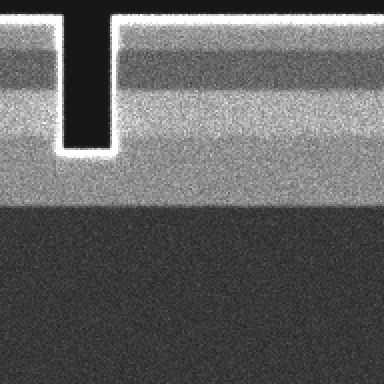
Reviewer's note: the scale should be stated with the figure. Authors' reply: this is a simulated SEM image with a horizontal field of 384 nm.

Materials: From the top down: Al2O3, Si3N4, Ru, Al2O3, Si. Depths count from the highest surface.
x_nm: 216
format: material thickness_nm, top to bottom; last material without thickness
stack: Al2O3 34, Si3N4 40, Ru 46, Al2O3 70, Si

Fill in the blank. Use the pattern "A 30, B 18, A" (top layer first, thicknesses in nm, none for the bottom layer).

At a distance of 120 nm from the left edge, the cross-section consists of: Al2O3 34, Si3N4 40, Ru 46, Al2O3 70, Si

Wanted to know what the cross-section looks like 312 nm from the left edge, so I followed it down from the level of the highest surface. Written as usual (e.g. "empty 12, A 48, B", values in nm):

Al2O3 34, Si3N4 40, Ru 46, Al2O3 70, Si